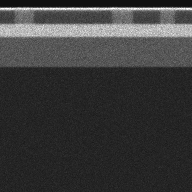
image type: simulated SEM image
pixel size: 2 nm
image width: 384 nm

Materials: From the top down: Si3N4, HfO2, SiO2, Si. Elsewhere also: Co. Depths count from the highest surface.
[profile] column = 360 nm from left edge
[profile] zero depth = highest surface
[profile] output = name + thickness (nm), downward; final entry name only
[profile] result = Si3N4 32, HfO2 26, SiO2 60, Si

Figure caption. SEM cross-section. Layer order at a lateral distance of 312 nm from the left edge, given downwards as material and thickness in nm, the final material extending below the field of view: Si3N4 32, HfO2 26, SiO2 60, Si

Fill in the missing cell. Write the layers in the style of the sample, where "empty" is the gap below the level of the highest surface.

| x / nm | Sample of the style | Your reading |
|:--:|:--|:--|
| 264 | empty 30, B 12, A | Co 32, HfO2 26, SiO2 60, Si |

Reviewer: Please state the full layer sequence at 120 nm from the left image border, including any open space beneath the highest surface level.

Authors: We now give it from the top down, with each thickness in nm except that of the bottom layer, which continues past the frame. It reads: Si3N4 32, HfO2 26, SiO2 60, Si